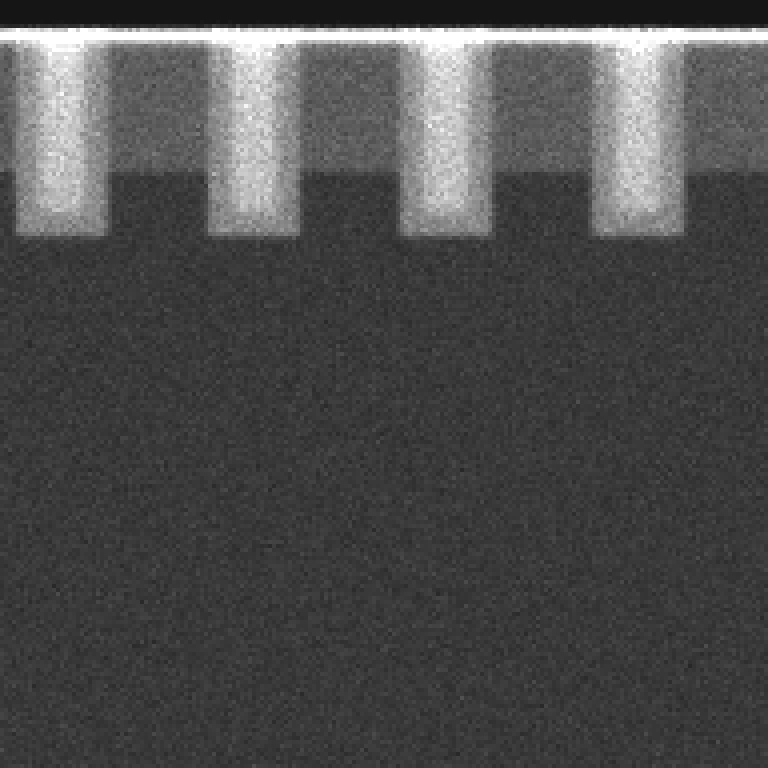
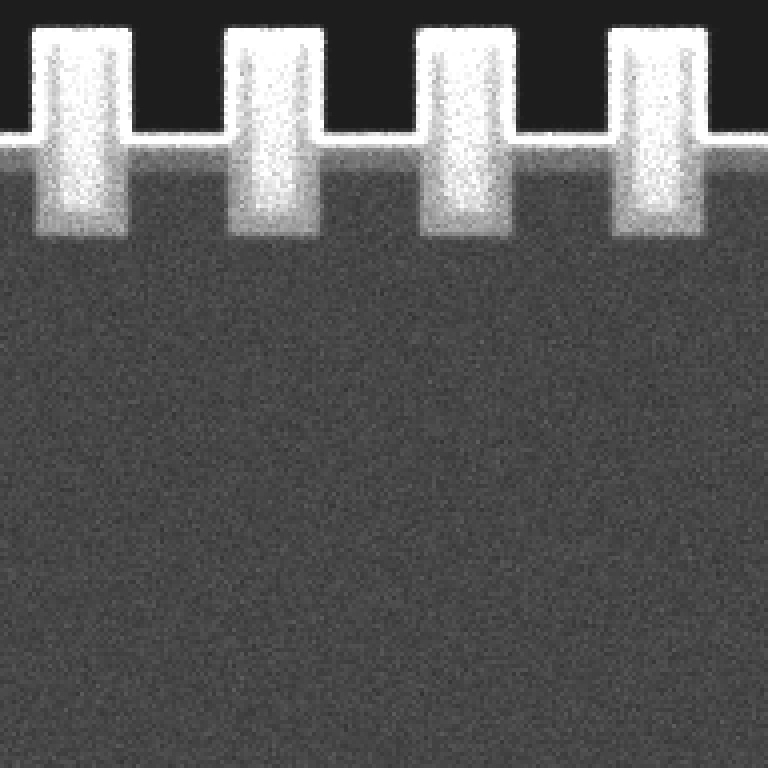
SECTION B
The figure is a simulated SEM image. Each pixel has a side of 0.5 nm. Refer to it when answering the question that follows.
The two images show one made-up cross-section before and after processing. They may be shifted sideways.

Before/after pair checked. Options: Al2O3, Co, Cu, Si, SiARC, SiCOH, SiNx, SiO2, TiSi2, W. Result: removed SiNx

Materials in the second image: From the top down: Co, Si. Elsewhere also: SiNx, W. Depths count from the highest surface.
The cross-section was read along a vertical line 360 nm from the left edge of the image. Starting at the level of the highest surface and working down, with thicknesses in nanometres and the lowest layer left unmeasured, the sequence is empty 52, SiNx 18, Si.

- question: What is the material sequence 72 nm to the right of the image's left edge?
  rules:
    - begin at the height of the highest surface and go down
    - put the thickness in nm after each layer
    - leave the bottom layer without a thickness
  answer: empty 52, SiNx 18, Si